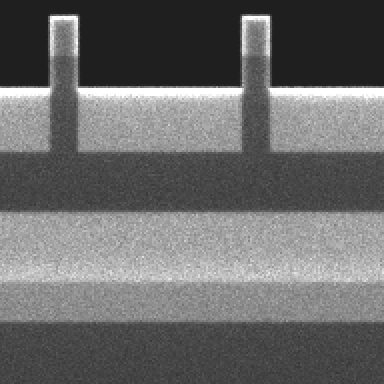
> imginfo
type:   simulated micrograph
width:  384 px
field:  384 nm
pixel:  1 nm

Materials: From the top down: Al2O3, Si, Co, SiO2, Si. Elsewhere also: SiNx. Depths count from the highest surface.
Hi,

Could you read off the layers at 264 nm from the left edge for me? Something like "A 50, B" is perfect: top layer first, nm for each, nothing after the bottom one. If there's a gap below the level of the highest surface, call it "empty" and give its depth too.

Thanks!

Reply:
SiNx 40, Si 156, Co 70, SiO2 40, Si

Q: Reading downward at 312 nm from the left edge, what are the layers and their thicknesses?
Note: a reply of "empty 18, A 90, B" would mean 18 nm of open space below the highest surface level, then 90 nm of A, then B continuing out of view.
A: empty 72, Al2O3 64, Si 60, Co 70, SiO2 40, Si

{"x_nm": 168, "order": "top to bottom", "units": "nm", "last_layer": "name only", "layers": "empty 72, Al2O3 64, Si 60, Co 70, SiO2 40, Si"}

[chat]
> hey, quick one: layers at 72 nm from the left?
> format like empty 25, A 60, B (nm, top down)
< SiNx 40, Si 156, Co 70, SiO2 40, Si